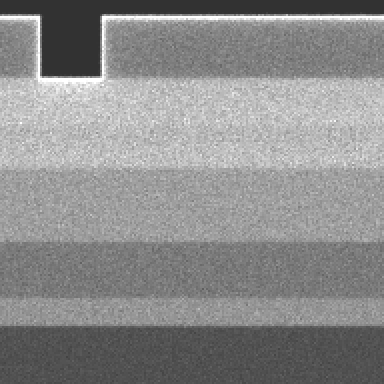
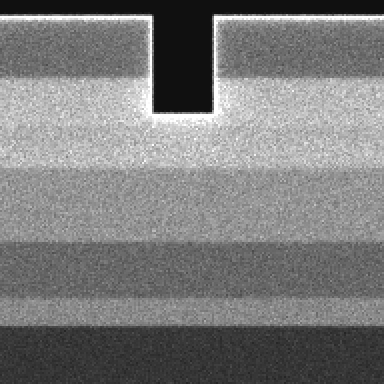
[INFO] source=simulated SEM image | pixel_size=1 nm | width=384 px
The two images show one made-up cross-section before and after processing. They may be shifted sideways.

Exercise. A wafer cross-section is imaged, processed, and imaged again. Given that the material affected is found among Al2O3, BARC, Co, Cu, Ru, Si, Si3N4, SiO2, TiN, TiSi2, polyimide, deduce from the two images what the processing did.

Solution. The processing removed Ru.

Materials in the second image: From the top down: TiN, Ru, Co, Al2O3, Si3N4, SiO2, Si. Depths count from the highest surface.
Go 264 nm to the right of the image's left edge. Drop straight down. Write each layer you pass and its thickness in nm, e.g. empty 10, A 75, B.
TiN 62, Ru 48, Co 42, Al2O3 74, Si3N4 56, SiO2 28, Si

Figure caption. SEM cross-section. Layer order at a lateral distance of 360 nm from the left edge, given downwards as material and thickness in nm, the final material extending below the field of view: TiN 62, Ru 48, Co 42, Al2O3 74, Si3N4 56, SiO2 28, Si